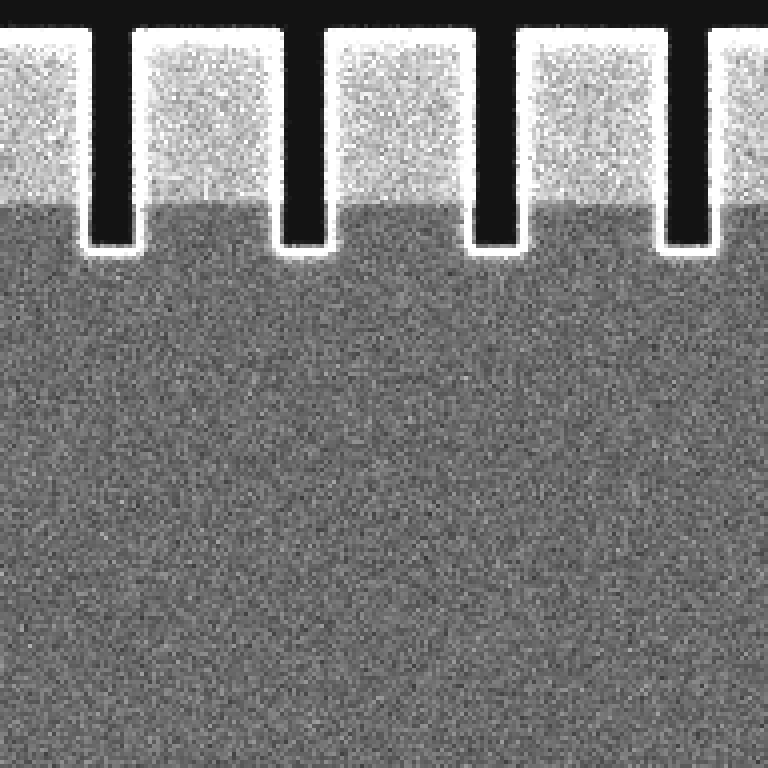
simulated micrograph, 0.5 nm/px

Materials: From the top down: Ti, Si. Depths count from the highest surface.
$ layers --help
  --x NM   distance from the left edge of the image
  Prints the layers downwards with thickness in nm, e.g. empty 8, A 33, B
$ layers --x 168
Ti 86, Si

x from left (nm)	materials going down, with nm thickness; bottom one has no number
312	Ti 86, Si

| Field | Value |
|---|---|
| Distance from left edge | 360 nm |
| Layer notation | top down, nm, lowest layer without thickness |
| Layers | Ti 86, Si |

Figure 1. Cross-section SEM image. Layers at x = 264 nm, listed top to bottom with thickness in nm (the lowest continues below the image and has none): Ti 86, Si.